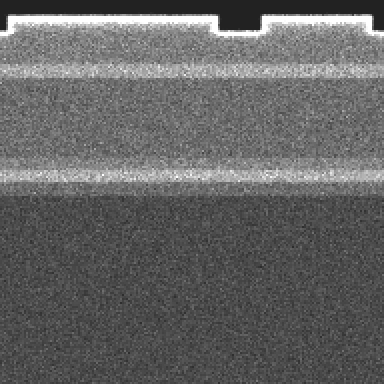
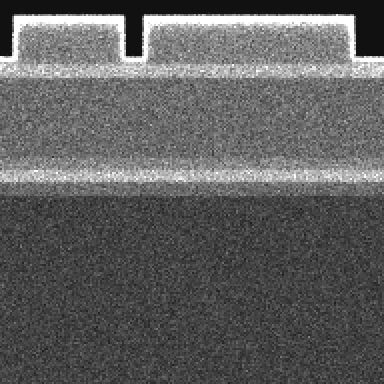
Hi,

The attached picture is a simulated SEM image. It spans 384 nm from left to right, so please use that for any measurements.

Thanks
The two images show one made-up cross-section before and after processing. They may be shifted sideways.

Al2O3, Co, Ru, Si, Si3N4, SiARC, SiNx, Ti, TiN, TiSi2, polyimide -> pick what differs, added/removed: TiN removed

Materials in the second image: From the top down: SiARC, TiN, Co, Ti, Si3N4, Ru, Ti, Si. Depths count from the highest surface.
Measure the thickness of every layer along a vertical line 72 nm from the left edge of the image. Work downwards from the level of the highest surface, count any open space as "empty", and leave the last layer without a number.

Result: SiARC 16, TiN 32, Co 14, Ti 80, Si3N4 12, Ru 12, Ti 14, Si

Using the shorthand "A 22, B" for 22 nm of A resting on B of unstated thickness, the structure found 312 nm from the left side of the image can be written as SiARC 16, TiN 32, Co 14, Ti 80, Si3N4 12, Ru 12, Ti 14, Si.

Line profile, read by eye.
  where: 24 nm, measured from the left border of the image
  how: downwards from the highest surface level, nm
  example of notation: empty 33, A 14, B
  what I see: SiARC 16, TiN 32, Co 14, Ti 80, Si3N4 12, Ru 12, Ti 14, Si